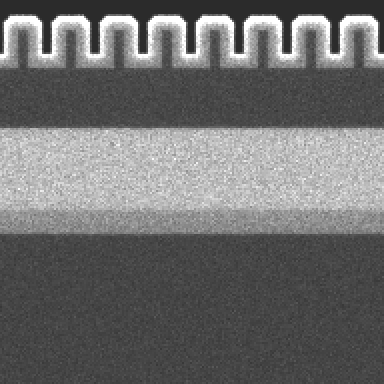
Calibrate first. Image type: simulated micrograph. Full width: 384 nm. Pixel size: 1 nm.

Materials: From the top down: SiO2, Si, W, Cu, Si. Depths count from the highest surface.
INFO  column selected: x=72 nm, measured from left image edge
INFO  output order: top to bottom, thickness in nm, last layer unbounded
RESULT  SiO2 14, Si 98, W 82, Cu 24, Si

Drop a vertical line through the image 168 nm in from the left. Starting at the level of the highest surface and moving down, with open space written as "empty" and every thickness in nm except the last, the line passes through SiO2 14, Si 98, W 82, Cu 24, Si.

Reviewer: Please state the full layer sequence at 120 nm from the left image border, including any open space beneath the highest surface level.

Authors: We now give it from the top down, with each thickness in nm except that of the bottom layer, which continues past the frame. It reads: SiO2 14, Si 98, W 82, Cu 24, Si